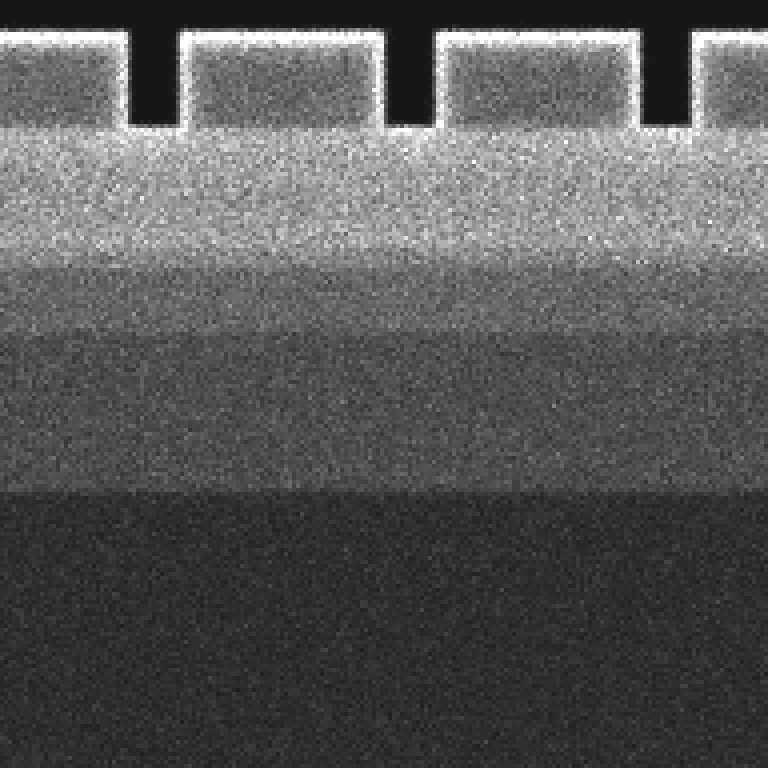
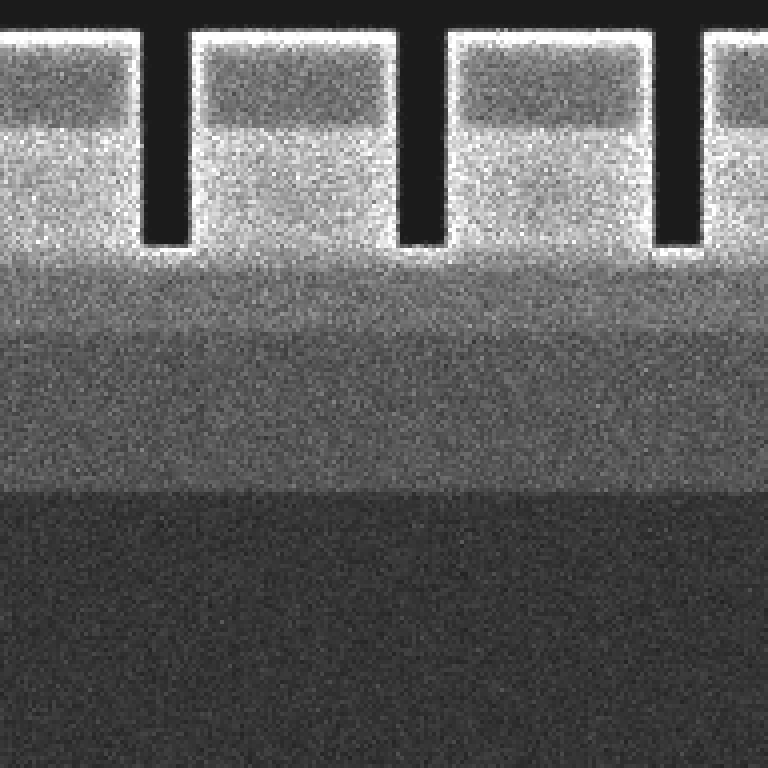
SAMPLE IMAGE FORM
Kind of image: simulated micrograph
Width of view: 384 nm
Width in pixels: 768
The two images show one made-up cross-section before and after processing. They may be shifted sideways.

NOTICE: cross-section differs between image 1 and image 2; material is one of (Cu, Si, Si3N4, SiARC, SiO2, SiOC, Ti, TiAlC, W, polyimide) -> removed: W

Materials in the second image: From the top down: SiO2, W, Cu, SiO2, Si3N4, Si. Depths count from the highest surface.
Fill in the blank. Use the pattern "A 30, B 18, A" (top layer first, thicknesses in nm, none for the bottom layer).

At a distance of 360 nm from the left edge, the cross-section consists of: SiO2 48, W 60, Cu 10, SiO2 32, Si3N4 80, Si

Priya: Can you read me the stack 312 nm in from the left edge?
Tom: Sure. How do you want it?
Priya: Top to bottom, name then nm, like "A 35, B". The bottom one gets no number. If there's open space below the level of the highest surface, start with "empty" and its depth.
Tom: SiO2 48, W 60, Cu 10, SiO2 32, Si3N4 80, Si